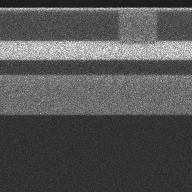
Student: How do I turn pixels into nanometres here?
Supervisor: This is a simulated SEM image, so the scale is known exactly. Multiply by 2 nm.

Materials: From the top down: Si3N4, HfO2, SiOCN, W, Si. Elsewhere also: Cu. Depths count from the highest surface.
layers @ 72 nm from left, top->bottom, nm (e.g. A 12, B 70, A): Si3N4 66, HfO2 38, SiOCN 30, W 80, Si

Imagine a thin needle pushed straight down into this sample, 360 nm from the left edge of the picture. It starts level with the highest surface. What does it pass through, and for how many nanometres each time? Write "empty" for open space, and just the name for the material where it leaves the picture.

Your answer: Si3N4 66, HfO2 38, SiOCN 30, W 80, Si